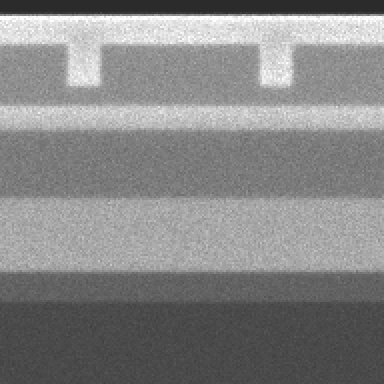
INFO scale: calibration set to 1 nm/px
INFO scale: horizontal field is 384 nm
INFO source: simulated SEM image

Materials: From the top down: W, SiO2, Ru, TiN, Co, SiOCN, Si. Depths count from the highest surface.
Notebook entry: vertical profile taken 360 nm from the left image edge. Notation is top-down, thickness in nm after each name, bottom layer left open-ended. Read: W 28, SiO2 62, Ru 24, TiN 68, Co 74, SiOCN 30, Si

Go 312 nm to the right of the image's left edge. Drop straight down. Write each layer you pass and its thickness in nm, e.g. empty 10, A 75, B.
W 28, SiO2 62, Ru 24, TiN 68, Co 74, SiOCN 30, Si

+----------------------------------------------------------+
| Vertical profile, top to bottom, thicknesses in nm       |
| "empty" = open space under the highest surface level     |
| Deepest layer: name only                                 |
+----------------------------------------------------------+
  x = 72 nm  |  W 70, SiO2 20, Ru 24, TiN 68, Co 74, SiOCN 30, Si